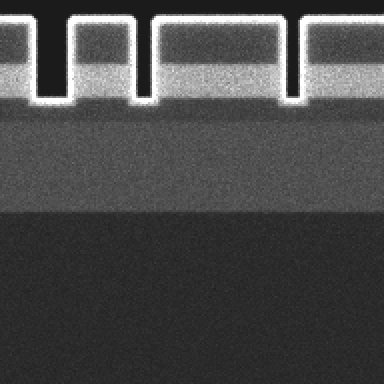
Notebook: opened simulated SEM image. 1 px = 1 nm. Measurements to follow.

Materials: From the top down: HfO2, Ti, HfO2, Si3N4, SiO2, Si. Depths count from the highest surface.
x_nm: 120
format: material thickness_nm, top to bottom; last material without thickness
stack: HfO2 8, Ti 40, HfO2 34, Si3N4 24, SiO2 90, Si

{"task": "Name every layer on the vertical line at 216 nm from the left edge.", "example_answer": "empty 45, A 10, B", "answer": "HfO2 8, Ti 40, HfO2 34, Si3N4 24, SiO2 90, Si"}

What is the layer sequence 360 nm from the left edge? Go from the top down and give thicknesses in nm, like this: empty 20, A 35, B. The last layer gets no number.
HfO2 8, Ti 40, HfO2 34, Si3N4 24, SiO2 90, Si